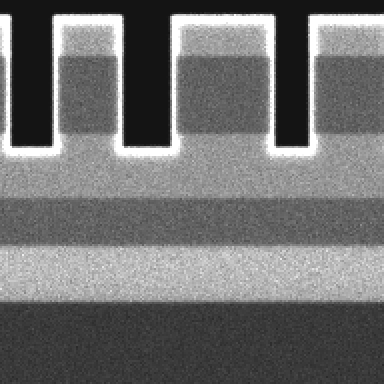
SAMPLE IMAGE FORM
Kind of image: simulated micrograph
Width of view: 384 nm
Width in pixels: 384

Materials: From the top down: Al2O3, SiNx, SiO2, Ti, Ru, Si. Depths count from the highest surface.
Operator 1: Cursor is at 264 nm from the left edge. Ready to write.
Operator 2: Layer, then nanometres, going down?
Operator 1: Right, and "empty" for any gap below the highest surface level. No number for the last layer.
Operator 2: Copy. Al2O3 40, SiNx 78, SiO2 64, Ti 48, Ru 56, Si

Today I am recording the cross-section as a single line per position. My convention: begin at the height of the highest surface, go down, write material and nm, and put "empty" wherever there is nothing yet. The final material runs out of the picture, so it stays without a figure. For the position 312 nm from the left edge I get Al2O3 40, SiNx 78, SiO2 64, Ti 48, Ru 56, Si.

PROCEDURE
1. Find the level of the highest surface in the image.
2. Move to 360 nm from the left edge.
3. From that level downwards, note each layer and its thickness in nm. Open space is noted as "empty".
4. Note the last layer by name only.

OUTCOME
Al2O3 40, SiNx 78, SiO2 64, Ti 48, Ru 56, Si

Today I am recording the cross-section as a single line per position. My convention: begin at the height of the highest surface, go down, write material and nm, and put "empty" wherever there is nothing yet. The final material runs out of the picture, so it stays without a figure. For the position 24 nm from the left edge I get empty 132, SiO2 50, Ti 48, Ru 56, Si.